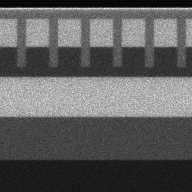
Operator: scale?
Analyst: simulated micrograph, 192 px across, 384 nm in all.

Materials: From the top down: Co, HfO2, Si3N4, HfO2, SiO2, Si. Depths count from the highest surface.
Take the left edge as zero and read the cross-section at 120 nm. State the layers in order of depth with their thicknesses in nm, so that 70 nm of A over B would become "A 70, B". Co 22, HfO2 56, Si3N4 60, HfO2 80, SiO2 86, Si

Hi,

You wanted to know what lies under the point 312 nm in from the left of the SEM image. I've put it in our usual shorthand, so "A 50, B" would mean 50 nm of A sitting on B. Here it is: Co 22, HfO2 56, Si3N4 60, HfO2 80, SiO2 86, Si